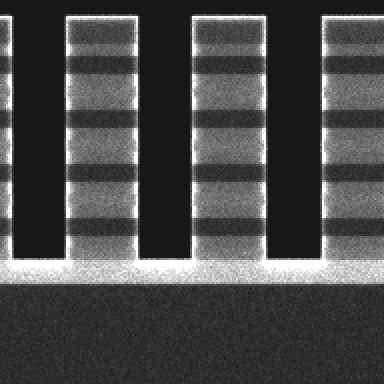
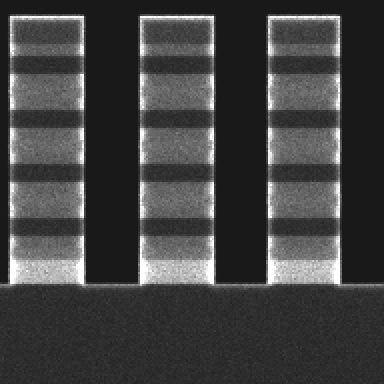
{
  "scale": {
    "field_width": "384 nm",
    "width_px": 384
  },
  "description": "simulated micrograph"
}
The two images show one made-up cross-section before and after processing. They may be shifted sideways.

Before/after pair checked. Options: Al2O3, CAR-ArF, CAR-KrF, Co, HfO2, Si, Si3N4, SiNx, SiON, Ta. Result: removed HfO2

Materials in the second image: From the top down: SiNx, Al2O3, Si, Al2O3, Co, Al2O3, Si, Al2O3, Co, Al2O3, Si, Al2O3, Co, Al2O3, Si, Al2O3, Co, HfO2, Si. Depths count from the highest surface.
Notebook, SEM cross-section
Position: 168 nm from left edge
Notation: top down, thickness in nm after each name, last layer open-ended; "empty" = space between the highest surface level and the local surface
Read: SiNx 28, Al2O3 12, Si 18, Al2O3 12, Co 12, Al2O3 12, Si 18, Al2O3 12, Co 12, Al2O3 12, Si 18, Al2O3 12, Co 12, Al2O3 12, Si 18, Al2O3 12, Co 12, HfO2 24, Si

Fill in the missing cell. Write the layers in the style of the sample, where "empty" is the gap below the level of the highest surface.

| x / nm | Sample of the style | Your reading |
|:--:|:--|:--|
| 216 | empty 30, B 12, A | empty 268, Si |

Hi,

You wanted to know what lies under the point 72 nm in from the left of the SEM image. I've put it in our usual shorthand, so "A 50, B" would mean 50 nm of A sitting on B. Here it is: SiNx 28, Al2O3 12, Si 18, Al2O3 12, Co 12, Al2O3 12, Si 18, Al2O3 12, Co 12, Al2O3 12, Si 18, Al2O3 12, Co 12, Al2O3 12, Si 18, Al2O3 12, Co 12, HfO2 24, Si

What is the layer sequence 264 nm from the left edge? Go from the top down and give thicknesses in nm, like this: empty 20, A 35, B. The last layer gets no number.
empty 268, Si